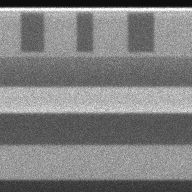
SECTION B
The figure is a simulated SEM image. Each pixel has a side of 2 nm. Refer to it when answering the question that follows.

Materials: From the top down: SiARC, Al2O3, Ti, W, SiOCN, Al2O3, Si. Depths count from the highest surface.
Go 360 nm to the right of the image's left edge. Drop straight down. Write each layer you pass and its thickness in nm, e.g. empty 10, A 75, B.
SiARC 10, Al2O3 88, Ti 60, W 52, SiOCN 64, Al2O3 70, Si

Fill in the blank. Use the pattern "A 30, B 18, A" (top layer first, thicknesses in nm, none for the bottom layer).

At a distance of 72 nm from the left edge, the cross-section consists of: SiARC 88, Al2O3 10, Ti 60, W 52, SiOCN 64, Al2O3 70, Si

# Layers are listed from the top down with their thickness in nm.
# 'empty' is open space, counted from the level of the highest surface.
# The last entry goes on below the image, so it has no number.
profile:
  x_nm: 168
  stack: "SiARC 88, Al2O3 10, Ti 60, W 52, SiOCN 64, Al2O3 70, Si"